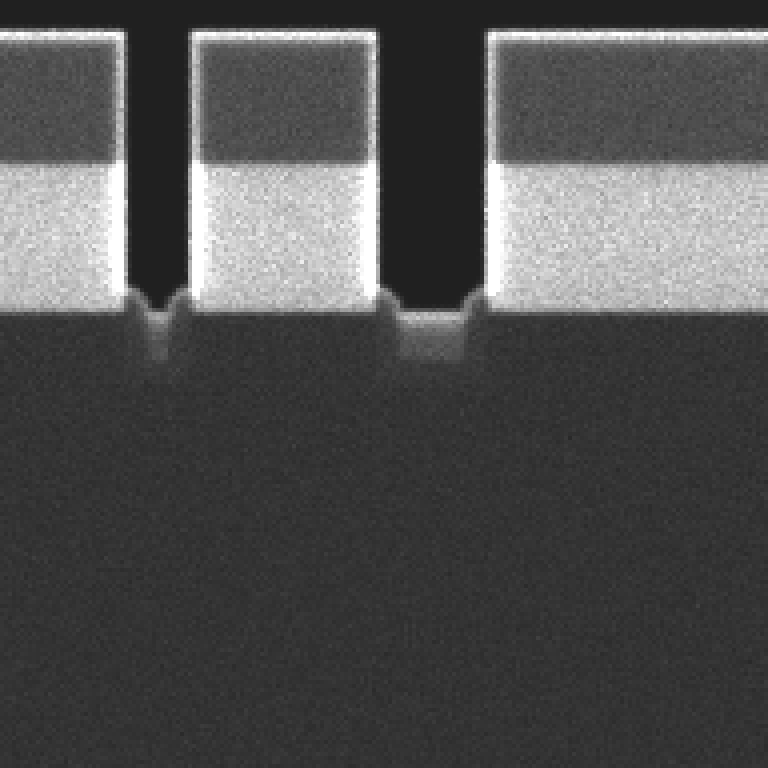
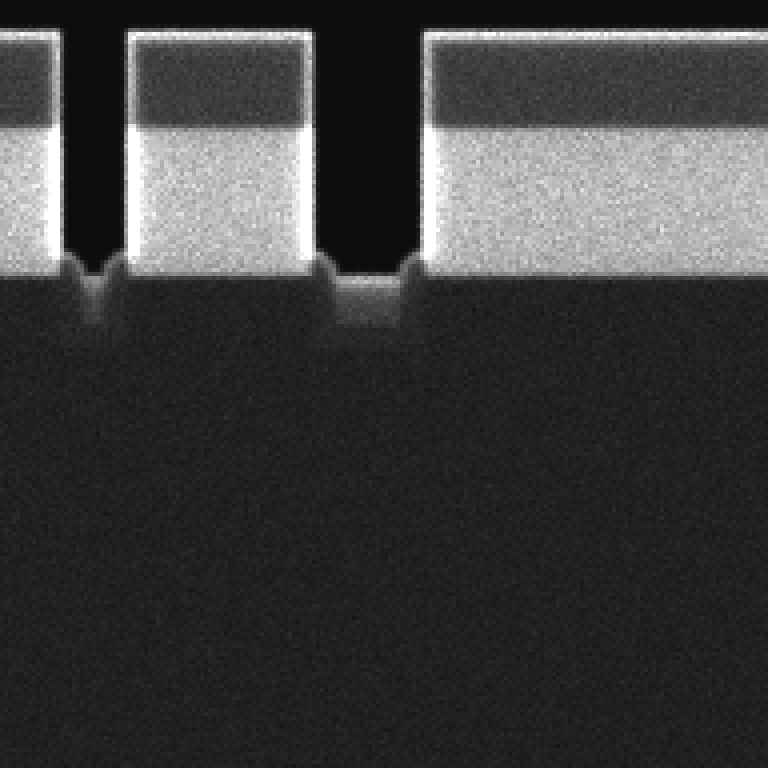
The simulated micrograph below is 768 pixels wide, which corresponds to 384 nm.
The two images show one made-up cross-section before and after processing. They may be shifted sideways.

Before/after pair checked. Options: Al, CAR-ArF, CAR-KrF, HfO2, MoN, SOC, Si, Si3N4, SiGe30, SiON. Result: removed Si3N4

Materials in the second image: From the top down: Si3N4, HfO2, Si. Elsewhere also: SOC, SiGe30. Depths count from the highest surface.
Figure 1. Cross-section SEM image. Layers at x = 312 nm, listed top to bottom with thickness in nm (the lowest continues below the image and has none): Si3N4 48, HfO2 74, Si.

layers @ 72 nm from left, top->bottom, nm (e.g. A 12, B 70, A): Si3N4 48, HfO2 74, Si